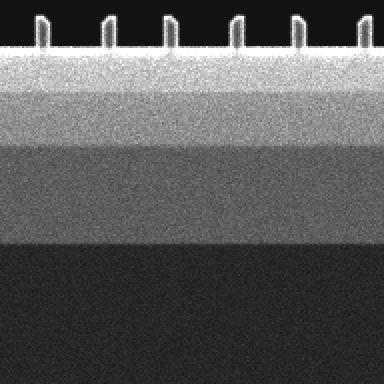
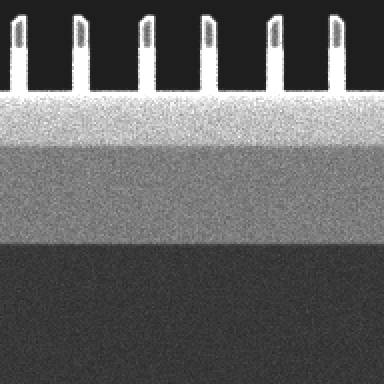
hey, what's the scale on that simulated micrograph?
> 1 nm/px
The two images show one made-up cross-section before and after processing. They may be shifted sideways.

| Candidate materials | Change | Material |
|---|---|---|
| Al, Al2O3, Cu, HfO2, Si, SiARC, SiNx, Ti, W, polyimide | removed | HfO2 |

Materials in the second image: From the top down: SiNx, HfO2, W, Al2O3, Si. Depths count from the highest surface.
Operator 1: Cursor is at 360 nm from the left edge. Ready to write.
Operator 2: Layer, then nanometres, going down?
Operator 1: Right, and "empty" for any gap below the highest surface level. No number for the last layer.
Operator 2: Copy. empty 76, W 54, Al2O3 98, Si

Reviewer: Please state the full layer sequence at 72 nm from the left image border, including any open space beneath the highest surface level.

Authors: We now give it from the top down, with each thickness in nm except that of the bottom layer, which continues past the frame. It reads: empty 76, W 54, Al2O3 98, Si